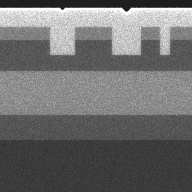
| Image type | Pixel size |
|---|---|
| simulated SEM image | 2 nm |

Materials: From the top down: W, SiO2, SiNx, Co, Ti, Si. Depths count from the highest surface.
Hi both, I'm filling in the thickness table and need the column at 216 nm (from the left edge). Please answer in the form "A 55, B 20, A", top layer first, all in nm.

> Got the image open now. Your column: W 38, SiO2 26, SiNx 62, Co 88, Ti 50, Si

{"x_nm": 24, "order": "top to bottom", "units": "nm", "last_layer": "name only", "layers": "W 38, SiO2 26, SiNx 62, Co 88, Ti 50, Si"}